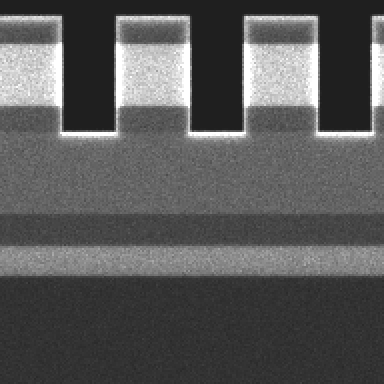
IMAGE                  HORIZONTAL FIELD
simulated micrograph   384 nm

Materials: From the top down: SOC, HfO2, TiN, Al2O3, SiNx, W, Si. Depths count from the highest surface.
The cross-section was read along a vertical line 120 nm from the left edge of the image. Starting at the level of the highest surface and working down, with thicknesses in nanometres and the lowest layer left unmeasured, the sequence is SOC 28, HfO2 62, TiN 26, Al2O3 82, SiNx 32, W 30, Si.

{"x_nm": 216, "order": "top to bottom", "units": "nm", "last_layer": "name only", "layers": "empty 116, Al2O3 82, SiNx 32, W 30, Si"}